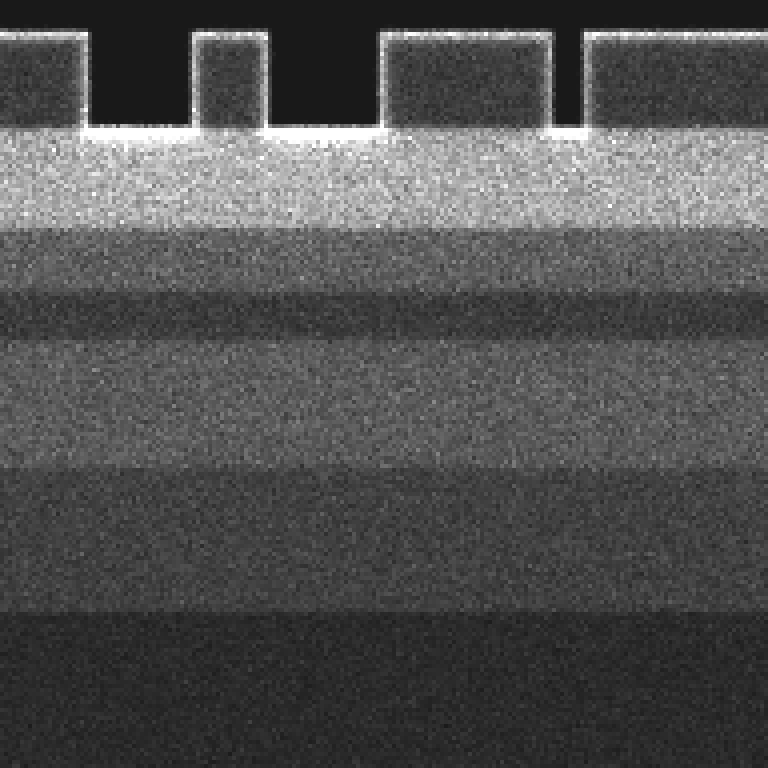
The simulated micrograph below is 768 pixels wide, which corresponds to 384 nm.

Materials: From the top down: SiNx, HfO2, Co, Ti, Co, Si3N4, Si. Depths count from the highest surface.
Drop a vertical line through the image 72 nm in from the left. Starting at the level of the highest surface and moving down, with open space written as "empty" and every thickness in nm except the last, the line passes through empty 48, HfO2 50, Co 32, Ti 24, Co 64, Si3N4 72, Si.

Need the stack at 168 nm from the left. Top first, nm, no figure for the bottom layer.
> empty 48, HfO2 50, Co 32, Ti 24, Co 64, Si3N4 72, Si